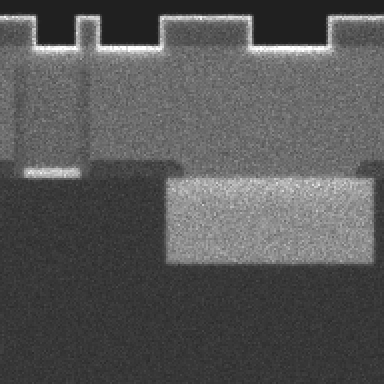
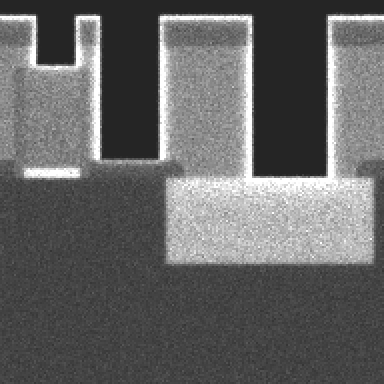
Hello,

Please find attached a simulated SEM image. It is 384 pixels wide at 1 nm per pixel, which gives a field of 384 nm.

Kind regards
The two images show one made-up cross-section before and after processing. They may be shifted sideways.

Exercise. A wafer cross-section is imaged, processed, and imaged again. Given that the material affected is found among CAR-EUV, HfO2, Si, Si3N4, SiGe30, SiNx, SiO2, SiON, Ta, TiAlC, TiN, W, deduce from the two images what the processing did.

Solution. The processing removed SiO2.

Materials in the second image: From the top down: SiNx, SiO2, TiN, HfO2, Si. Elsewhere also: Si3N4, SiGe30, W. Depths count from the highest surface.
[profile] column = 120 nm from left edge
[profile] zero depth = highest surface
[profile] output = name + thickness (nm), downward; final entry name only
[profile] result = empty 144, SiGe30 18, Si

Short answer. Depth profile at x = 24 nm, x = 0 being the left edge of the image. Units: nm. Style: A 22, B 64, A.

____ SiNx 30, SiO2 20, TiN 102, HfO2 10, Si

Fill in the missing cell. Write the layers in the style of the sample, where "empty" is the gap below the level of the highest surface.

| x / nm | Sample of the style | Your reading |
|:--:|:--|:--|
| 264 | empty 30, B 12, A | empty 162, W 86, Si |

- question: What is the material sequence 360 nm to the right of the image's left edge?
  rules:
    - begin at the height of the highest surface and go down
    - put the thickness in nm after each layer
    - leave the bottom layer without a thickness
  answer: SiNx 30, SiO2 118, SiGe30 14, W 86, Si